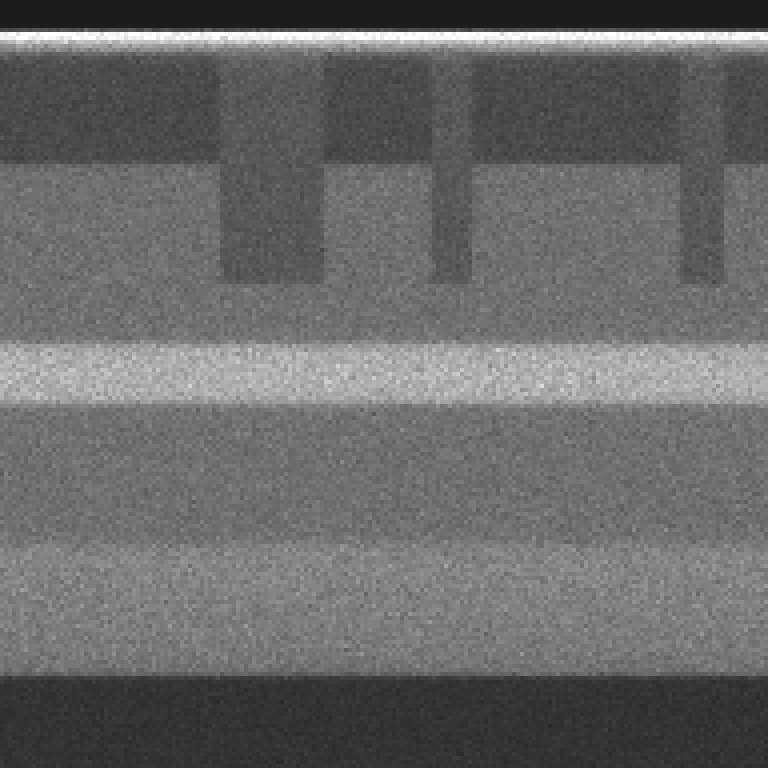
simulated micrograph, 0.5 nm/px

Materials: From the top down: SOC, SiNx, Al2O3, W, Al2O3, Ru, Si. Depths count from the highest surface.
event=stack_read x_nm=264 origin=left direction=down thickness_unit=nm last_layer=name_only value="SOC 8, SiNx 58, Al2O3 90, W 30, Al2O3 70, Ru 66, Si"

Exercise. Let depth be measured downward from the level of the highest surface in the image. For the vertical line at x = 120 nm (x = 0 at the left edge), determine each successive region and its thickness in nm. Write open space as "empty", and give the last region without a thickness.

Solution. SOC 126, Al2O3 30, W 30, Al2O3 70, Ru 66, Si